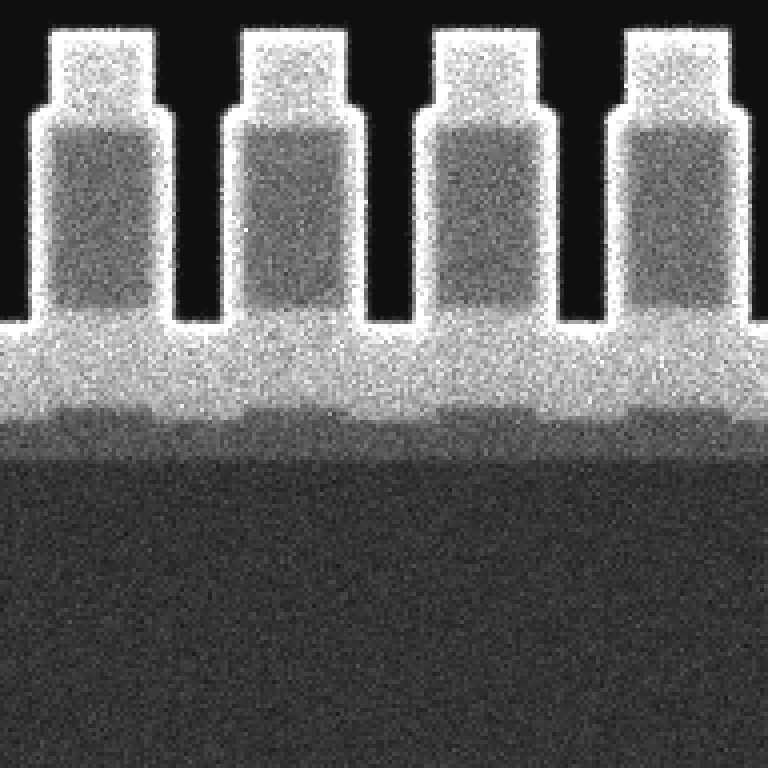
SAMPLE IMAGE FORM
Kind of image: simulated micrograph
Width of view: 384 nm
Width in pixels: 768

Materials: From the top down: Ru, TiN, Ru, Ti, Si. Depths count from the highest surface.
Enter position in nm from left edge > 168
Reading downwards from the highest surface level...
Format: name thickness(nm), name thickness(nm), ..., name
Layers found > Ru 48, TiN 90, Ru 50, Ti 26, Si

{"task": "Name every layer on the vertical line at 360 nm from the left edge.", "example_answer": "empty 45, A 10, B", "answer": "Ru 48, TiN 90, Ru 50, Ti 26, Si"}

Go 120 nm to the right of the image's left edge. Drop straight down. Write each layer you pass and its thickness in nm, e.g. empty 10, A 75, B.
empty 38, Ru 156, Ti 20, Si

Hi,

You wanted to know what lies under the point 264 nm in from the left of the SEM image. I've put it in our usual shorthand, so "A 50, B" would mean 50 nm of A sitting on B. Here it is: Ru 48, TiN 90, Ru 50, Ti 26, Si